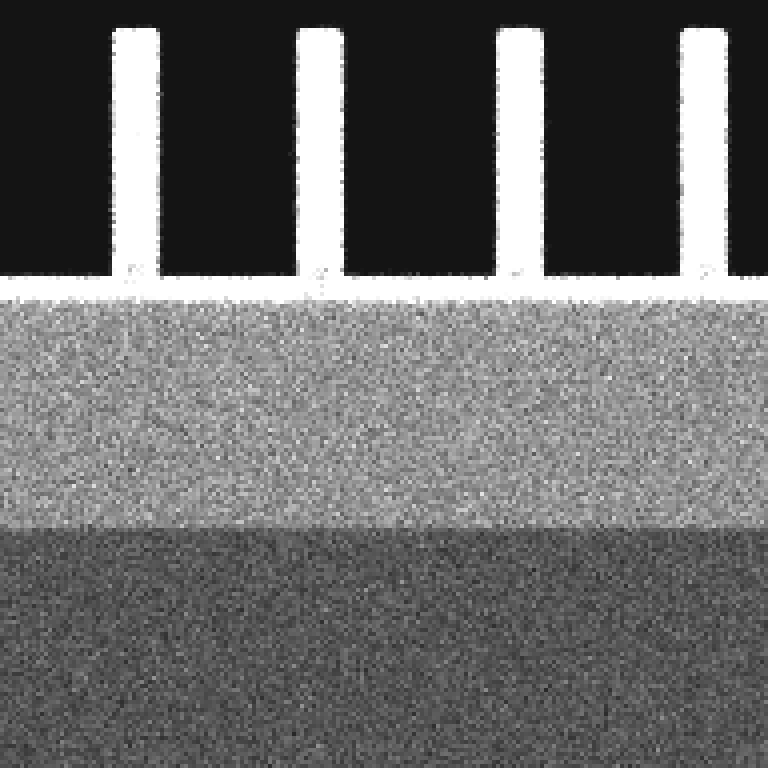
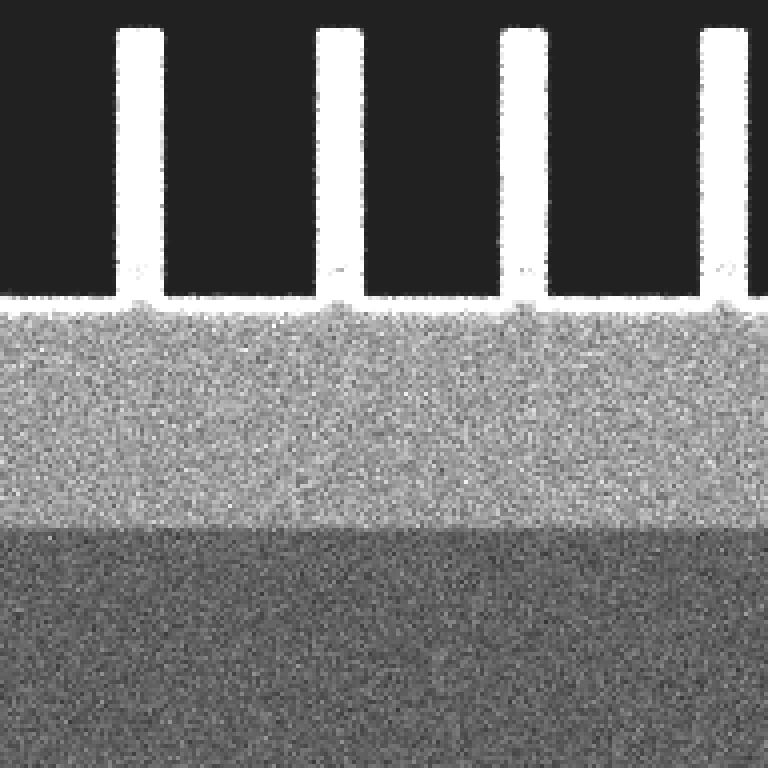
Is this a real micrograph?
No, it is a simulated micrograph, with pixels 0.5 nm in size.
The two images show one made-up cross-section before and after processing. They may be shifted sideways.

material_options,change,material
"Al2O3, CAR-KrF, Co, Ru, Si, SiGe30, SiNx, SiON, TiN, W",removed,Co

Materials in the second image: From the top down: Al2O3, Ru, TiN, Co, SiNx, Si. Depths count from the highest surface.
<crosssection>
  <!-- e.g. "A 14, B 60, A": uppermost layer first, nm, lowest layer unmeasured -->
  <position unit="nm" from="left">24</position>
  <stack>empty 134, SiNx 114, Si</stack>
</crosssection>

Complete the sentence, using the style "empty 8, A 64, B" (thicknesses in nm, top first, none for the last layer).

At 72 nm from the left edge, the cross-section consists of Al2O3 28, Ru 86, TiN 10, Co 10, SiNx 114, Si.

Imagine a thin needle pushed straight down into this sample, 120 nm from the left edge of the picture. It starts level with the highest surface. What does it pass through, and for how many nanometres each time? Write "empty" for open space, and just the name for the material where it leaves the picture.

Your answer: empty 134, SiNx 114, Si